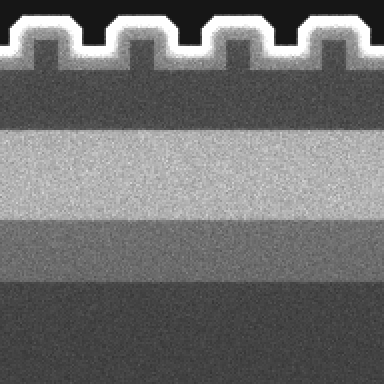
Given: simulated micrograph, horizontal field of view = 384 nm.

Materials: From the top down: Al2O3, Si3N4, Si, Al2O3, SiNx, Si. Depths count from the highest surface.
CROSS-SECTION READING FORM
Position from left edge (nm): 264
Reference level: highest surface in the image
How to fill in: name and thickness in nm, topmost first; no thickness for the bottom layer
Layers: empty 4, Al2O3 38, Si3N4 12, Si 60, Al2O3 90, SiNx 62, Si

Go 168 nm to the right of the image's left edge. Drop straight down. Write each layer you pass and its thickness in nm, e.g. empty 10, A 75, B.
empty 4, Al2O3 38, Si3N4 12, Si 60, Al2O3 90, SiNx 62, Si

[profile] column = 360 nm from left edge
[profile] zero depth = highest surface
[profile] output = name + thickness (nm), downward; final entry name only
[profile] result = empty 4, Al2O3 38, Si3N4 12, Si 60, Al2O3 90, SiNx 62, Si